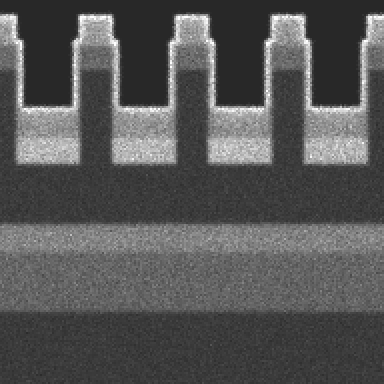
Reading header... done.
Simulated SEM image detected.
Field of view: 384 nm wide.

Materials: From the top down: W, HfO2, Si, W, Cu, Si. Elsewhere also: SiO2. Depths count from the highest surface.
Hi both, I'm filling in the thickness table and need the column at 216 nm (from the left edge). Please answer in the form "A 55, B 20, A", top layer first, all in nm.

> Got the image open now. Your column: empty 92, W 30, HfO2 26, Si 60, W 28, Cu 60, Si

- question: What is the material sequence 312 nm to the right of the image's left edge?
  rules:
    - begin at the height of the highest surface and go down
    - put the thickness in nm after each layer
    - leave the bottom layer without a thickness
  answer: empty 92, W 30, HfO2 26, Si 60, W 28, Cu 60, Si